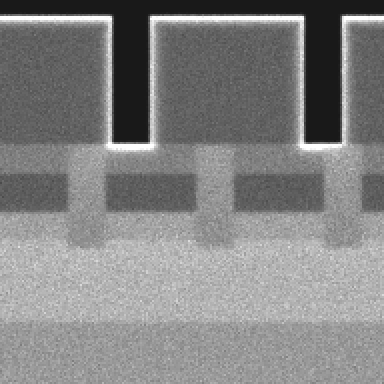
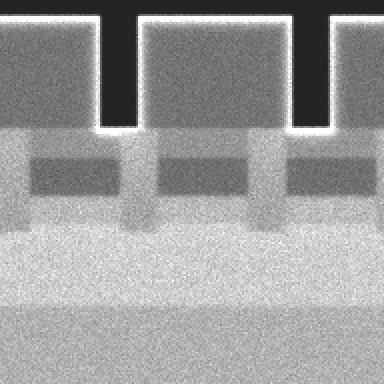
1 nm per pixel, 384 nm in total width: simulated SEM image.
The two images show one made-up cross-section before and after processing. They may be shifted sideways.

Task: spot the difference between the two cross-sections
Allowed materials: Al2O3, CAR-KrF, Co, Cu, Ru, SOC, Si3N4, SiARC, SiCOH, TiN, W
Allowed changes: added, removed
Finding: removed SiARC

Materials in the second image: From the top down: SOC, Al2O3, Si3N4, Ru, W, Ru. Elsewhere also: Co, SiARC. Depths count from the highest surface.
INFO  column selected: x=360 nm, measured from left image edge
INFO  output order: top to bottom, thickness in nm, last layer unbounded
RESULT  SOC 112, Al2O3 30, Si3N4 38, Ru 28, W 82, Ru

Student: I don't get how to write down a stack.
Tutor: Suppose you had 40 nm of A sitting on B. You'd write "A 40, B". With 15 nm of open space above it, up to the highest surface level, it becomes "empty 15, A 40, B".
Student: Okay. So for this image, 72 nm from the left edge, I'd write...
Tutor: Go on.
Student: SOC 112, Al2O3 30, Si3N4 38, Ru 28, W 82, Ru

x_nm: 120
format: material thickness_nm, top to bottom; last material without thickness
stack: empty 112, Co 104, W 74, Ru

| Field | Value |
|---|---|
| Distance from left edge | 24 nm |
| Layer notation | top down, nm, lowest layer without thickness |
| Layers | SOC 112, Co 104, W 74, Ru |